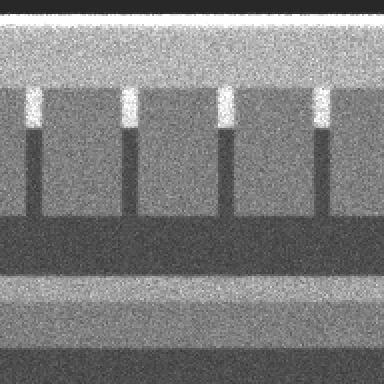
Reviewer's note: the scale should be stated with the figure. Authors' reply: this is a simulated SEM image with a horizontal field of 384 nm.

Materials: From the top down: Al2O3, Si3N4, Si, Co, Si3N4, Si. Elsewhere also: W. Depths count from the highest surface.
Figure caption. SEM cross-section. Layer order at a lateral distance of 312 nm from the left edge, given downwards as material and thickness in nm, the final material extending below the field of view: Al2O3 72, Si3N4 128, Si 60, Co 26, Si3N4 46, Si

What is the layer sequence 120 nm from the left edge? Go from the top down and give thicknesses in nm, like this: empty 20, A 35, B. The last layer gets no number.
Al2O3 72, Si3N4 128, Si 60, Co 26, Si3N4 46, Si